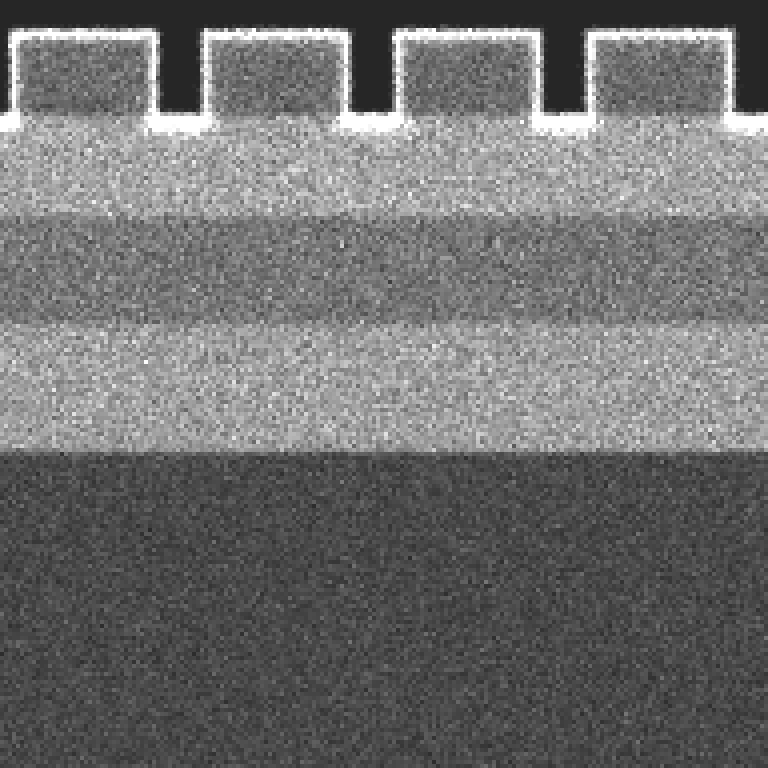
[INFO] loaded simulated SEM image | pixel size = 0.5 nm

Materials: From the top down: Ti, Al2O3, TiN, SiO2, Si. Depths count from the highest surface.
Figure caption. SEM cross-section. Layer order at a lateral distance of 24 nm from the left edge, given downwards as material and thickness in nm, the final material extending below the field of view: Ti 42, Al2O3 50, TiN 54, SiO2 64, Si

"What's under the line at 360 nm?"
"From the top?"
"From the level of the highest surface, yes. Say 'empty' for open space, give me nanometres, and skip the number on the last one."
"Ti 42, Al2O3 50, TiN 54, SiO2 64, Si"